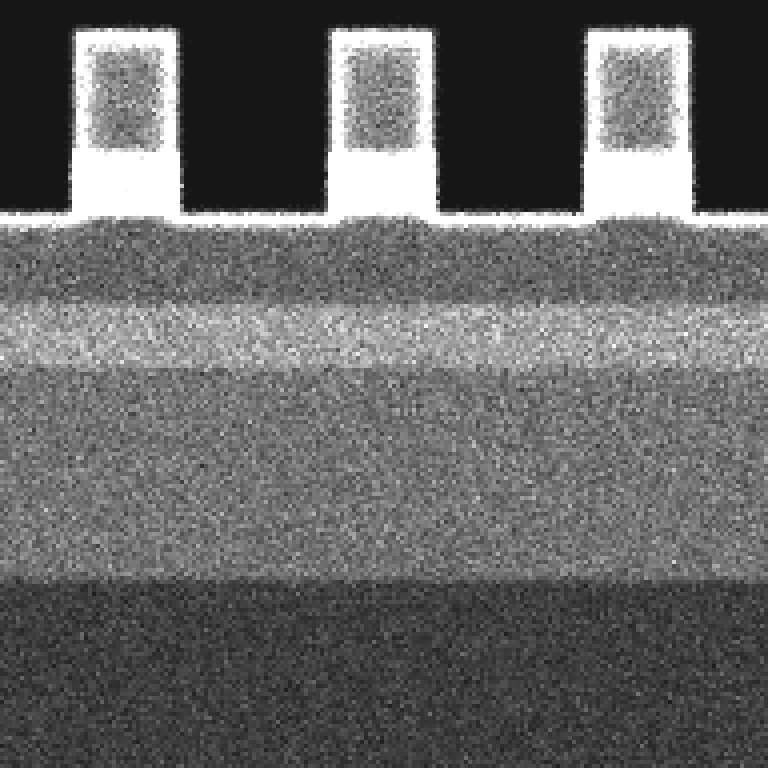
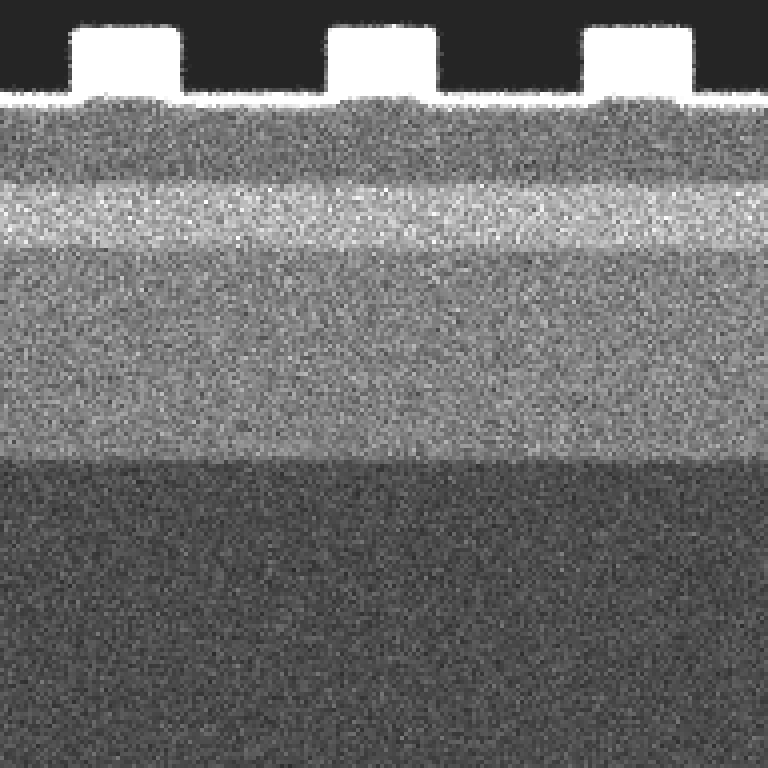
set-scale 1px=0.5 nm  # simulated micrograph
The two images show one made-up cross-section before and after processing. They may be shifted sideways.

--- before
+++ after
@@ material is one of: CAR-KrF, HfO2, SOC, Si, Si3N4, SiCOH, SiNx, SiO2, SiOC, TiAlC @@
SOC removed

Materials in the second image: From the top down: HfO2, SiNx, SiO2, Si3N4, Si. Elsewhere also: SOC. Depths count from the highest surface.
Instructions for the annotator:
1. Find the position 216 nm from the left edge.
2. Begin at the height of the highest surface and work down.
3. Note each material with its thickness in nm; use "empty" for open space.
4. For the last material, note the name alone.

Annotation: empty 32, SiNx 44, SiO2 32, Si3N4 106, Si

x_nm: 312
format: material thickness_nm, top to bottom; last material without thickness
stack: HfO2 32, SiNx 44, SiO2 32, Si3N4 106, Si